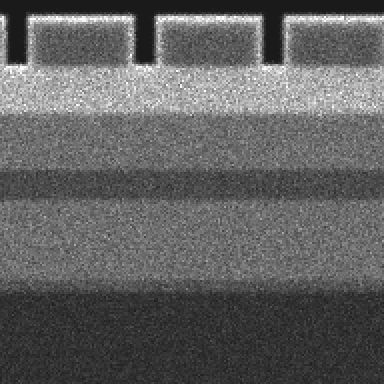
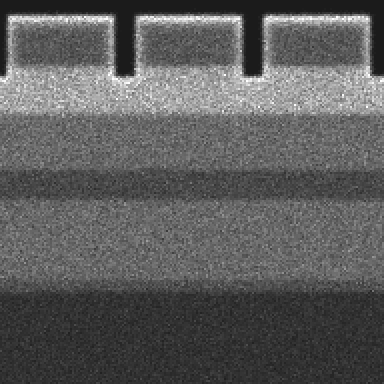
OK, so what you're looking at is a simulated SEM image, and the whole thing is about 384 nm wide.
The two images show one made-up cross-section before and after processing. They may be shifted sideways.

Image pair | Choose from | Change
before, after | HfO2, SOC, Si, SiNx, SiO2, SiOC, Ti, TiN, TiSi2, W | W (removed)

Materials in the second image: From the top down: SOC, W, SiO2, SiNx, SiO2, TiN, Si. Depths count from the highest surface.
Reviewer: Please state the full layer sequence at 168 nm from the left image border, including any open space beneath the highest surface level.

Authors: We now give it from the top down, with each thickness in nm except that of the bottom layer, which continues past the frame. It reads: SOC 50, W 48, SiO2 56, SiNx 30, SiO2 80, TiN 12, Si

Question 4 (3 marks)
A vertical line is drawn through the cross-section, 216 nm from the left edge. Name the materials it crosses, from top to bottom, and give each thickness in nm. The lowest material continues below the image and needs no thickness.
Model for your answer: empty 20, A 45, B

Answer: SOC 50, W 48, SiO2 56, SiNx 30, SiO2 80, TiN 12, Si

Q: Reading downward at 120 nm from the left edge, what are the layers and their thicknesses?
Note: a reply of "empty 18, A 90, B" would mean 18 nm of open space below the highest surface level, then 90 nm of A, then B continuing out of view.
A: empty 62, W 36, SiO2 56, SiNx 30, SiO2 80, TiN 12, Si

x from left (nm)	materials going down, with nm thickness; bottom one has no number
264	SOC 50, W 48, SiO2 56, SiNx 30, SiO2 80, TiN 12, Si